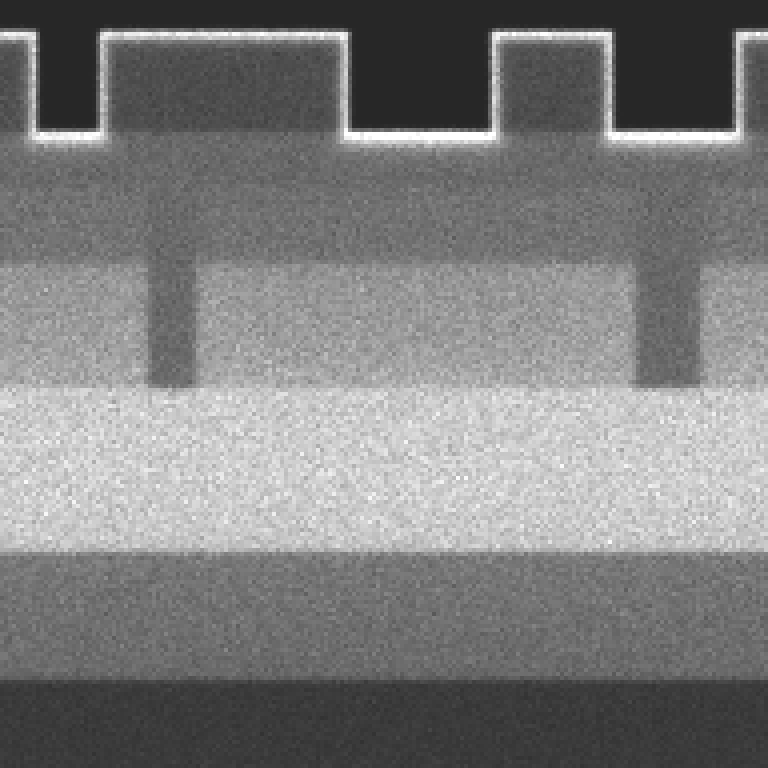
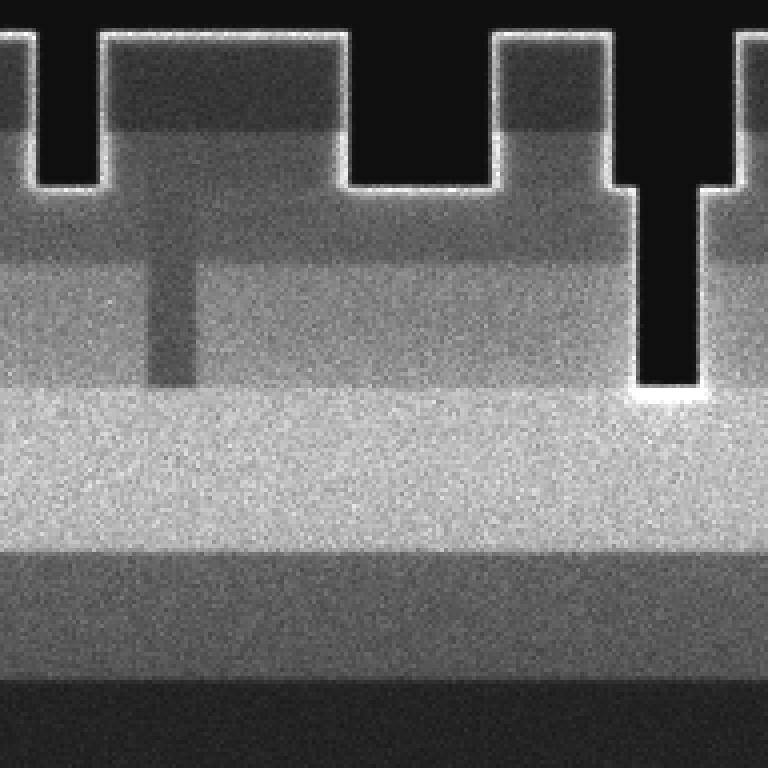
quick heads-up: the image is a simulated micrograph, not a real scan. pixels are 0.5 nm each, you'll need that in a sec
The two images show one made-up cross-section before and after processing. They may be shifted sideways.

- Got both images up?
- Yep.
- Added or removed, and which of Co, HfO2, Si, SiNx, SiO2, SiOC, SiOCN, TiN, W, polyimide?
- removed, SiO2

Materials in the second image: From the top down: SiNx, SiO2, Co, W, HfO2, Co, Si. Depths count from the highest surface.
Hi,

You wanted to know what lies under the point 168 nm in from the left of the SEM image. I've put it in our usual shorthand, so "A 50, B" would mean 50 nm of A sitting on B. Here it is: SiNx 50, SiO2 28, Co 38, W 62, HfO2 82, Co 64, Si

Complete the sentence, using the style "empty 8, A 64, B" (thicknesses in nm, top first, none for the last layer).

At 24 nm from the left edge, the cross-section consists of empty 78, Co 38, W 62, HfO2 82, Co 64, Si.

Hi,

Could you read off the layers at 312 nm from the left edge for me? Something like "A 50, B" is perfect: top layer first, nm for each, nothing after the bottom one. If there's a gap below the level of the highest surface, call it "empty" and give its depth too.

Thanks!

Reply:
empty 78, Co 38, W 62, HfO2 82, Co 64, Si